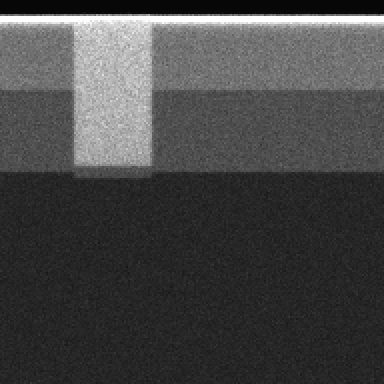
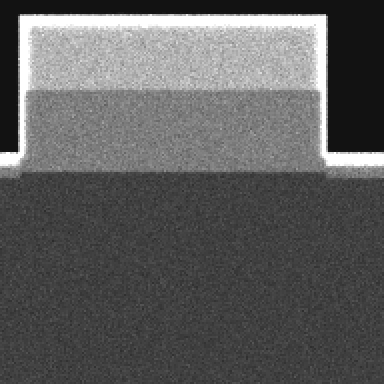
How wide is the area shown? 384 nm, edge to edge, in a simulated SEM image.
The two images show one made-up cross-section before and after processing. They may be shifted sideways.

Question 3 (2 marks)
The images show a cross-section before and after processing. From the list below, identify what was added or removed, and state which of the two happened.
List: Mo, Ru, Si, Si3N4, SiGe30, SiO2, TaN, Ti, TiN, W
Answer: W was removed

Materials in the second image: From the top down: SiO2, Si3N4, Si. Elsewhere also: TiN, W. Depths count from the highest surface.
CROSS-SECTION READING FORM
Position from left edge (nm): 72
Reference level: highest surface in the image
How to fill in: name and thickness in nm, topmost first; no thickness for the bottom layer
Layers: SiO2 74, Si3N4 82, Si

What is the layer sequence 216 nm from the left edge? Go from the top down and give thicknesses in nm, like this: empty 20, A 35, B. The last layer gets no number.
SiO2 74, Si3N4 82, Si